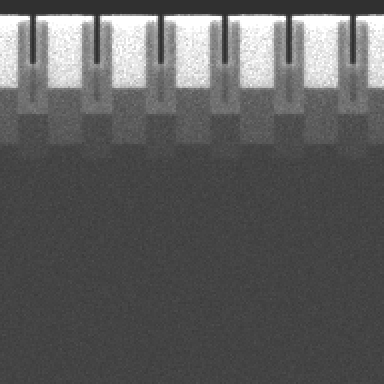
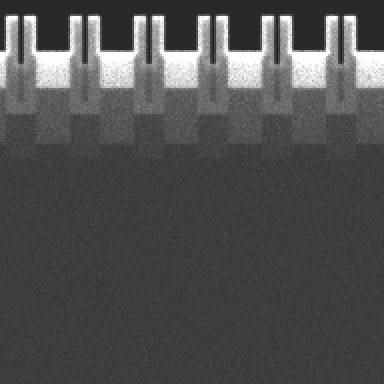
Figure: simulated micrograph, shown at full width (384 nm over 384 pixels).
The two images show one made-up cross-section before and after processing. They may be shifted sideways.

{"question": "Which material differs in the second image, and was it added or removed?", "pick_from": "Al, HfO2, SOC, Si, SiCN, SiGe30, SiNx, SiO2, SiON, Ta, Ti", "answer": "HfO2, removed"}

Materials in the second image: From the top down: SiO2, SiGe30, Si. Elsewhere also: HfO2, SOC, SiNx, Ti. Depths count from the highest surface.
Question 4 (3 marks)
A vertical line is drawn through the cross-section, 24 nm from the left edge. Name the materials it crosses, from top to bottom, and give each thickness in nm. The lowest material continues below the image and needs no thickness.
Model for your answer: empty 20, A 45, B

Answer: SiO2 98, SiGe30 44, Si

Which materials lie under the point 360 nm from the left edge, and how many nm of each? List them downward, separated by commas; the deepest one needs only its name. empty 36, HfO2 36, Ti 56, Si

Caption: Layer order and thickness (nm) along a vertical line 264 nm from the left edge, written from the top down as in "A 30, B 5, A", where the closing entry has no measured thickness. SiO2 98, SiGe30 44, Si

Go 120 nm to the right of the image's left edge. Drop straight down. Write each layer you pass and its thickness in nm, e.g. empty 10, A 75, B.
empty 36, HfO2 36, Ti 56, Si